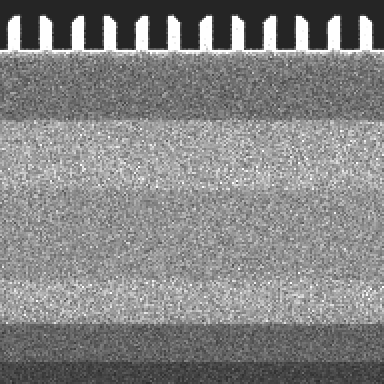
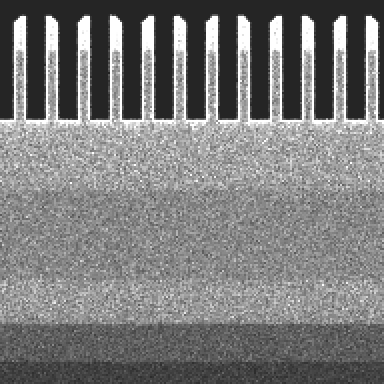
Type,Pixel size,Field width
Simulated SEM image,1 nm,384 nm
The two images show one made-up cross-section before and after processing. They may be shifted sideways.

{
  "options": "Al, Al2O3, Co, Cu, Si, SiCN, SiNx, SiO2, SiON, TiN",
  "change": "removed",
  "material": "TiN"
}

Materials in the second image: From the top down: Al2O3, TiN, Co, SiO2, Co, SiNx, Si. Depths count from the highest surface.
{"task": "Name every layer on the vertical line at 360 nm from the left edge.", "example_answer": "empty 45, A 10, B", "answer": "empty 104, Co 70, SiO2 90, Co 44, SiNx 38, Si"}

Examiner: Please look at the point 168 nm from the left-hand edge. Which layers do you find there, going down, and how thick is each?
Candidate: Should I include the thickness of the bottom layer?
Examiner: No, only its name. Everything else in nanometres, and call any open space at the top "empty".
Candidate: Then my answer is empty 104, Co 70, SiO2 90, Co 44, SiNx 38, Si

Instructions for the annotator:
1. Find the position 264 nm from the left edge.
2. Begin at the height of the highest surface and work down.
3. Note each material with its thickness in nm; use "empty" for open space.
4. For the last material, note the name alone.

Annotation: empty 104, Co 70, SiO2 90, Co 44, SiNx 38, Si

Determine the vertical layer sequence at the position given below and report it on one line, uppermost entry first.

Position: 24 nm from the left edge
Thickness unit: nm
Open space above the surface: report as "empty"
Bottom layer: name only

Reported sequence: Al2O3 34, TiN 70, Co 70, SiO2 90, Co 44, SiNx 38, Si